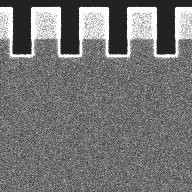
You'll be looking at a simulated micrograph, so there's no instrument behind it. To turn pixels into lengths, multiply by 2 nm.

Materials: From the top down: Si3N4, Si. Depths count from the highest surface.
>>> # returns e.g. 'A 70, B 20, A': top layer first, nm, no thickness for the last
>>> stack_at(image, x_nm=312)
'empty 94, Si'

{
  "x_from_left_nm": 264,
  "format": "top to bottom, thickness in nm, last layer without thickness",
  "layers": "Si3N4 62, Si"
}